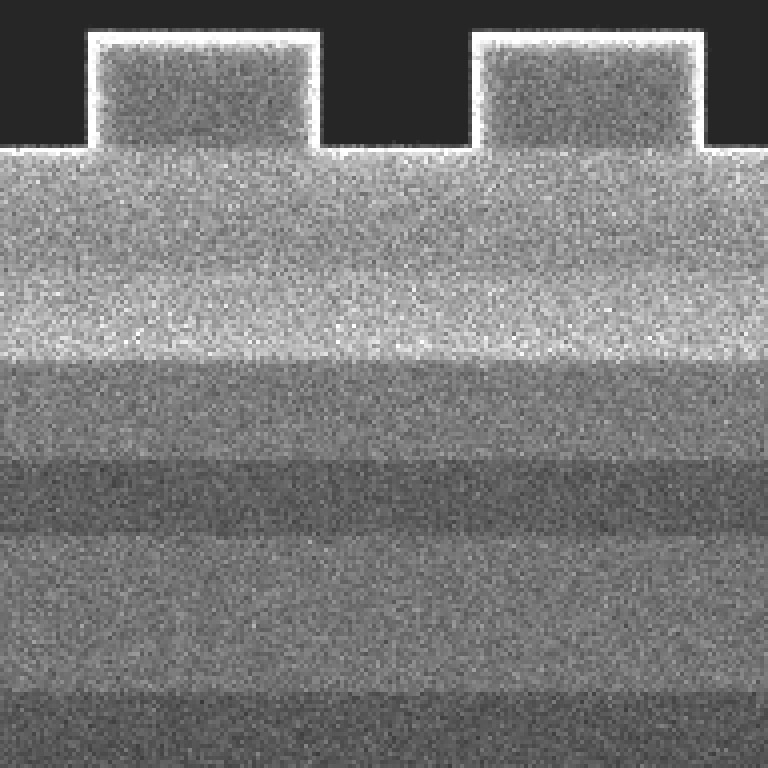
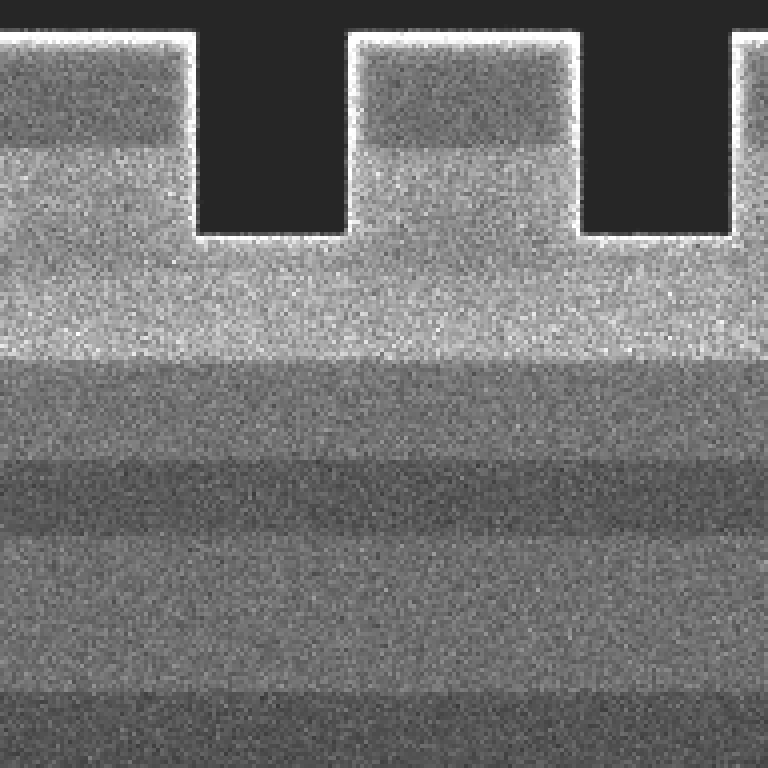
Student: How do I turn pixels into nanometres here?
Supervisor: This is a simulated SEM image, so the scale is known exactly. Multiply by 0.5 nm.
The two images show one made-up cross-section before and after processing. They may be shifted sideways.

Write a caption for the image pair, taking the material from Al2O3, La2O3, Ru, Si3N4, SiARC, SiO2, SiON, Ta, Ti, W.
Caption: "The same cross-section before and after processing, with Ru removed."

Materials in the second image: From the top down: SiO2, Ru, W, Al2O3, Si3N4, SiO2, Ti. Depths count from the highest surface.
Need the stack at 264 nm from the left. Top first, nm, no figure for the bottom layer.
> SiO2 58, Ru 62, W 44, Al2O3 50, Si3N4 38, SiO2 78, Ti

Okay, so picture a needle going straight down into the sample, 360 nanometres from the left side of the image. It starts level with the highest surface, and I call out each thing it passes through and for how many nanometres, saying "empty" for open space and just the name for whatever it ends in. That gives empty 102, Ru 18, W 44, Al2O3 50, Si3N4 38, SiO2 78, Ti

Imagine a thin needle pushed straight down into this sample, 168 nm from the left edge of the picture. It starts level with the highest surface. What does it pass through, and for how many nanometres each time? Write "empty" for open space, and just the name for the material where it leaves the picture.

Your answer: empty 102, Ru 18, W 44, Al2O3 50, Si3N4 38, SiO2 78, Ti